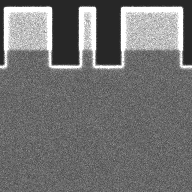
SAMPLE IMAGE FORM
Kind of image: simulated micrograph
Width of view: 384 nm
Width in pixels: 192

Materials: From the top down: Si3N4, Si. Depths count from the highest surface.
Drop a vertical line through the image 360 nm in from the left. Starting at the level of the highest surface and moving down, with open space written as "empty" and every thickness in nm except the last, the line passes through Si3N4 84, Si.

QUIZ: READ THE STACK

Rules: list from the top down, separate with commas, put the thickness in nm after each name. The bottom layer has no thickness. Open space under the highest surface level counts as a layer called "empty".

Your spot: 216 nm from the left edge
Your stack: empty 116, Si